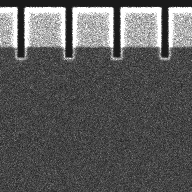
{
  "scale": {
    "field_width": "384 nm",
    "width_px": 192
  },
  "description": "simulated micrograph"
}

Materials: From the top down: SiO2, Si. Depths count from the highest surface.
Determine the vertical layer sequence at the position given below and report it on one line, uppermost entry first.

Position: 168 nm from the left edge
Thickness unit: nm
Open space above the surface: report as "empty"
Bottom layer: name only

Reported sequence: SiO2 78, Si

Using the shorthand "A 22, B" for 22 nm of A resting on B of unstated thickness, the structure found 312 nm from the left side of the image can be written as SiO2 78, Si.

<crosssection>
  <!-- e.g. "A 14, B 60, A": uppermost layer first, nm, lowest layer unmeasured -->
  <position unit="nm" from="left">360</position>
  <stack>SiO2 78, Si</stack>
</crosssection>